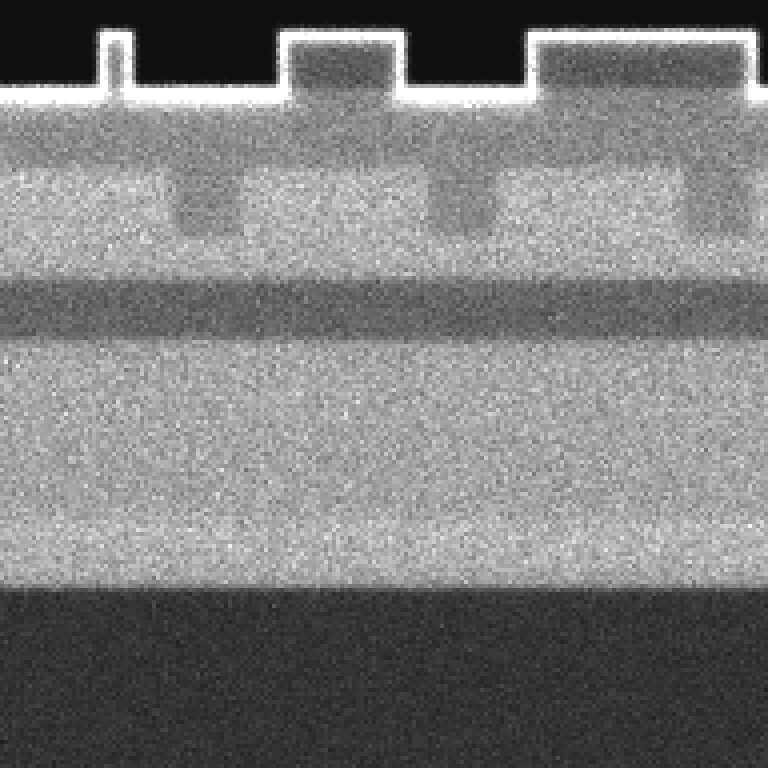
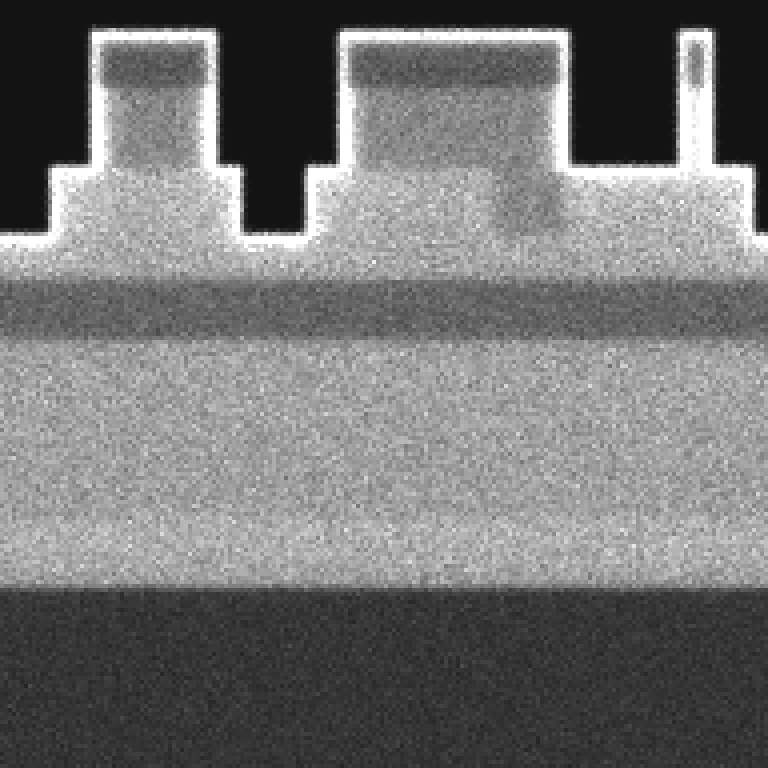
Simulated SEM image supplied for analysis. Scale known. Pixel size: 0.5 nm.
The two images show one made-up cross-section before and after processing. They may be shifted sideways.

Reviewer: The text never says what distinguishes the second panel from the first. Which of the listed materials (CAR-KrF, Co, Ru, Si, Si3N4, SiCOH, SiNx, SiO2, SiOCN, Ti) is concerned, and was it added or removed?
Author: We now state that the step removed SiO2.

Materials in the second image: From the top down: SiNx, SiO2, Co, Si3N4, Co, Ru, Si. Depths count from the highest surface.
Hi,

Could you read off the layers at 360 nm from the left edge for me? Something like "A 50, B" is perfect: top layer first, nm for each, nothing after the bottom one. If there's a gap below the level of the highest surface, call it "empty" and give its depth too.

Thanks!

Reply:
empty 68, Co 56, Si3N4 30, Co 90, Ru 34, Si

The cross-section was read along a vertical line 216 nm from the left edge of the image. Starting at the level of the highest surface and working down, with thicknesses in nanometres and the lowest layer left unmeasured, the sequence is SiNx 28, SiO2 40, Co 56, Si3N4 30, Co 90, Ru 34, Si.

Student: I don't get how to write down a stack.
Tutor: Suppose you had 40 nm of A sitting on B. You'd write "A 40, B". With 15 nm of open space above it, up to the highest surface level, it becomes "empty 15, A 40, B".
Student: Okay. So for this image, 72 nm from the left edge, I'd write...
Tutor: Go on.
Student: SiNx 28, SiO2 40, Co 56, Si3N4 30, Co 90, Ru 34, Si